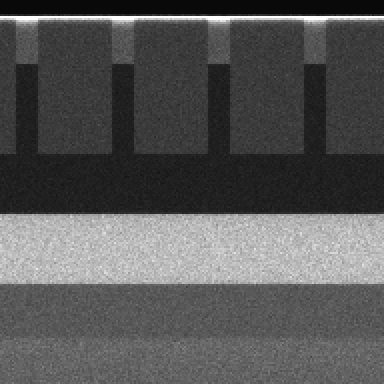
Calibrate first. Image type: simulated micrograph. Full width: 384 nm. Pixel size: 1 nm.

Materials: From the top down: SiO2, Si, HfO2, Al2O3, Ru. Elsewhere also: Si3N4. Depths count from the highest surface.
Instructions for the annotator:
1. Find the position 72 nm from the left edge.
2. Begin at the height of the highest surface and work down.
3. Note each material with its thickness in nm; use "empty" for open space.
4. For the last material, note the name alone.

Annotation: Si3N4 138, Si 60, HfO2 70, Al2O3 54, Ru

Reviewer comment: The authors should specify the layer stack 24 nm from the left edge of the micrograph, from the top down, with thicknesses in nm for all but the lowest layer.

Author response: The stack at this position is SiO2 48, Si 150, HfO2 70, Al2O3 54, Ru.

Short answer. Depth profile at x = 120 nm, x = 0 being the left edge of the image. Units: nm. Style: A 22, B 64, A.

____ SiO2 48, Si 150, HfO2 70, Al2O3 54, Ru